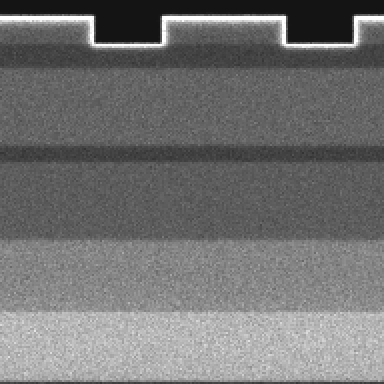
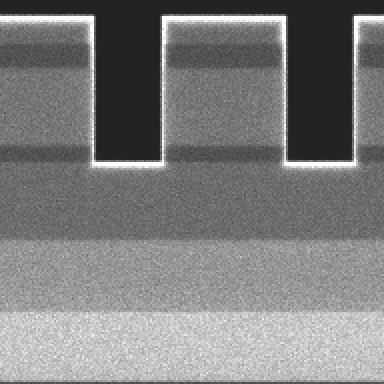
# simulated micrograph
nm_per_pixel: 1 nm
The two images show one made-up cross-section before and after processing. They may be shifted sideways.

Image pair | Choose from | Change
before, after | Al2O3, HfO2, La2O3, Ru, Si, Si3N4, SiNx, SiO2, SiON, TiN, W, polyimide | Ru and Si3N4 and TiN (removed)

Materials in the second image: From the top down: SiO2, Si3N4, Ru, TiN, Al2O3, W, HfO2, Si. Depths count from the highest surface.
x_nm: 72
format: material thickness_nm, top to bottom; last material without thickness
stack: SiO2 28, Si3N4 24, Ru 78, TiN 16, Al2O3 78, W 72, HfO2 70, Si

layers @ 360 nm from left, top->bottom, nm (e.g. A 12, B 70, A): SiO2 28, Si3N4 24, Ru 78, TiN 16, Al2O3 78, W 72, HfO2 70, Si